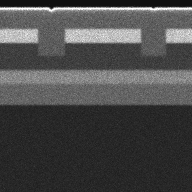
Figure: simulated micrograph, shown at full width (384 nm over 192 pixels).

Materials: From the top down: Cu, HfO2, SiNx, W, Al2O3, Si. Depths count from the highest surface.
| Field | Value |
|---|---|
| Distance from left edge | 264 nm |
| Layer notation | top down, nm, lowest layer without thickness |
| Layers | Cu 42, HfO2 28, SiNx 54, W 28, Al2O3 42, Si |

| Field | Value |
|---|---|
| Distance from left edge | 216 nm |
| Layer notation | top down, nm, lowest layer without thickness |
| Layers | Cu 42, HfO2 28, SiNx 54, W 28, Al2O3 42, Si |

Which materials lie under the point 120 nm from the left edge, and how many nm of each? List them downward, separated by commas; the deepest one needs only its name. Cu 96, SiNx 28, W 28, Al2O3 42, Si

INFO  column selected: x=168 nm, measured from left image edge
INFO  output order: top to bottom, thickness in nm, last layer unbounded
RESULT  Cu 42, HfO2 28, SiNx 54, W 28, Al2O3 42, Si